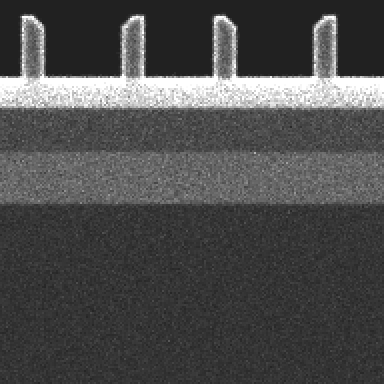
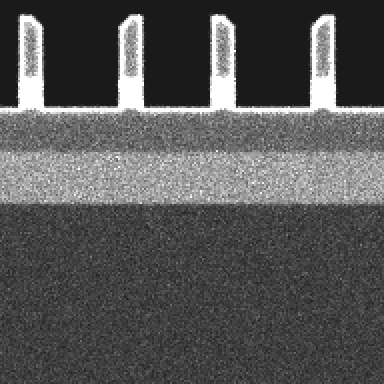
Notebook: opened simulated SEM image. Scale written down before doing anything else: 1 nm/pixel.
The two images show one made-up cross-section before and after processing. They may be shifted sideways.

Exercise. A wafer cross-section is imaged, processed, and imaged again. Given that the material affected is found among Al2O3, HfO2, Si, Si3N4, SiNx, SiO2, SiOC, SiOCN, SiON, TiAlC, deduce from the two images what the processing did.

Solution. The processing removed HfO2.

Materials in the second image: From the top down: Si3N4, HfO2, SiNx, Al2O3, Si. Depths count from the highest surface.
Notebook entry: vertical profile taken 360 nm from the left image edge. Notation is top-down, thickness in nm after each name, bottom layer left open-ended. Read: empty 92, SiNx 44, Al2O3 52, Si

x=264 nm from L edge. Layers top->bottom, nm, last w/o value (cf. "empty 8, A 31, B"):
empty 92, SiNx 44, Al2O3 52, Si